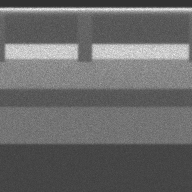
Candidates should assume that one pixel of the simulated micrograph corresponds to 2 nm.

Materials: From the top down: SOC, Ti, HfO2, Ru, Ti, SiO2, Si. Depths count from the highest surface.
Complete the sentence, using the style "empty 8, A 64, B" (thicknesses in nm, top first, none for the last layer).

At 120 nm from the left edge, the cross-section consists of SOC 10, Ti 62, HfO2 30, Ru 60, Ti 36, SiO2 74, Si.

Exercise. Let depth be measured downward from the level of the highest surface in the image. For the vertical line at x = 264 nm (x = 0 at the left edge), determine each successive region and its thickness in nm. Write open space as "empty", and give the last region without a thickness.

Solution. SOC 10, Ti 62, HfO2 30, Ru 60, Ti 36, SiO2 74, Si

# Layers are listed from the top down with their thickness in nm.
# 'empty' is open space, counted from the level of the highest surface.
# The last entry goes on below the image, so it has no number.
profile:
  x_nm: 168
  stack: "SOC 108, Ru 54, Ti 36, SiO2 74, Si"